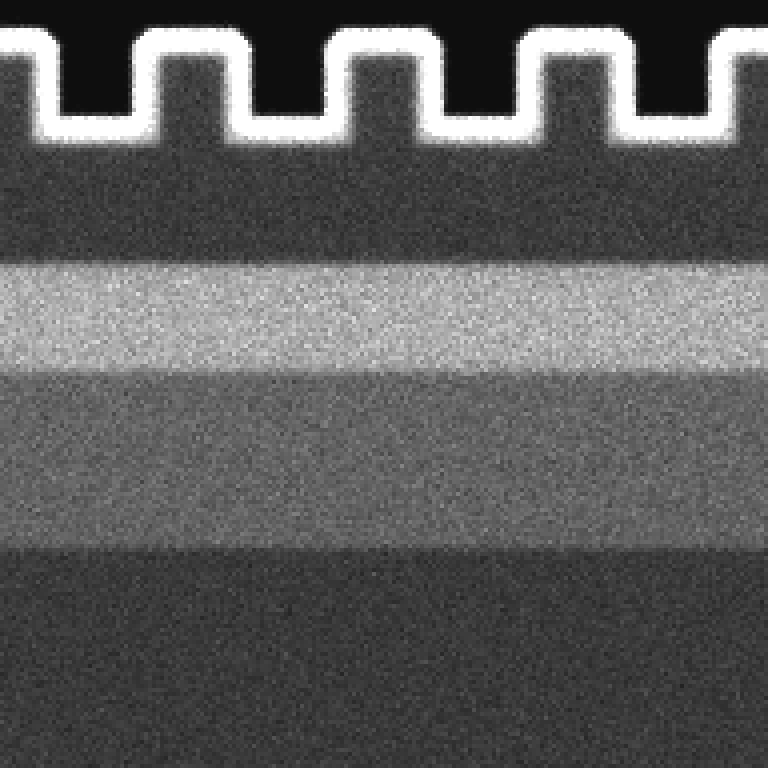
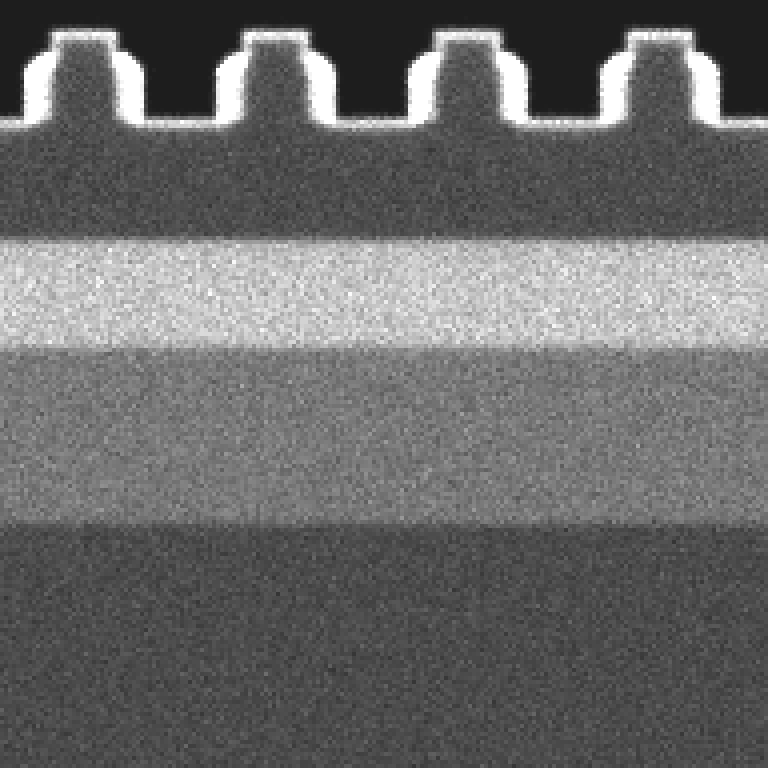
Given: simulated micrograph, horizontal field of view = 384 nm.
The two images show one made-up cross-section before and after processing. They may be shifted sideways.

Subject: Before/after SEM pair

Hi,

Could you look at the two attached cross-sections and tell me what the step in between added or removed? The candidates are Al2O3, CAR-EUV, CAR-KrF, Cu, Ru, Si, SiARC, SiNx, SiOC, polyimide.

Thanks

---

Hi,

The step removed Al2O3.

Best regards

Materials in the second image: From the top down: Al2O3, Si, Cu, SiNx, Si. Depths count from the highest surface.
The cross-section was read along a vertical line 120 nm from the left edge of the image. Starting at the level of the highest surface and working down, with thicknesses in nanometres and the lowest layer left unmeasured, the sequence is empty 12, Al2O3 32, Si 60, Cu 54, SiNx 88, Si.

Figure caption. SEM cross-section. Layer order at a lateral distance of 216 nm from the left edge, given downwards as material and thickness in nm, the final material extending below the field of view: empty 12, Al2O3 32, Si 60, Cu 54, SiNx 88, Si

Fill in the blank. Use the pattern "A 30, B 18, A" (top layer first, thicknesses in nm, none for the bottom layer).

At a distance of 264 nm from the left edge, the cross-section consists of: empty 44, Si 60, Cu 54, SiNx 88, Si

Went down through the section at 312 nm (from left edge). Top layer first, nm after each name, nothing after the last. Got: empty 12, Al2O3 32, Si 60, Cu 54, SiNx 88, Si